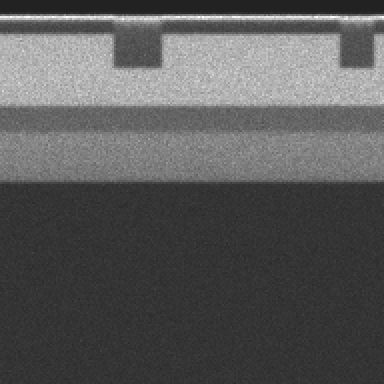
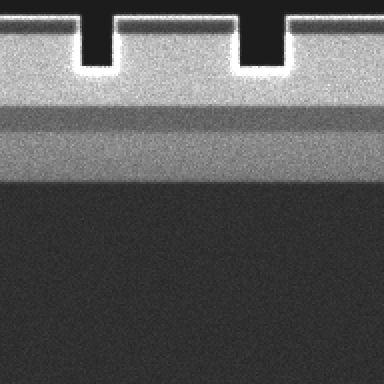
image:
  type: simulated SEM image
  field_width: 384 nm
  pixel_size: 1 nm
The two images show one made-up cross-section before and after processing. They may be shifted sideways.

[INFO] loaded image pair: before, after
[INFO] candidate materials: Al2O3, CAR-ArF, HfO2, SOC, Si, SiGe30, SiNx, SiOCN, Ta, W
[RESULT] removed SOC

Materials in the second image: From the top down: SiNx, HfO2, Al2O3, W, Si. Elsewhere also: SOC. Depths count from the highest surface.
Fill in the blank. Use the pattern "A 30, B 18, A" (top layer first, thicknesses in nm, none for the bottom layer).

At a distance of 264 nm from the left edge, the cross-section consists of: empty 52, HfO2 38, Al2O3 26, W 50, Si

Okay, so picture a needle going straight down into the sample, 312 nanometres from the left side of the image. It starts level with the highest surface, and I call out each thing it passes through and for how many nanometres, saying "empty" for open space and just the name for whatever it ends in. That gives SiNx 18, HfO2 72, Al2O3 26, W 50, Si